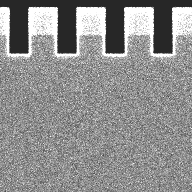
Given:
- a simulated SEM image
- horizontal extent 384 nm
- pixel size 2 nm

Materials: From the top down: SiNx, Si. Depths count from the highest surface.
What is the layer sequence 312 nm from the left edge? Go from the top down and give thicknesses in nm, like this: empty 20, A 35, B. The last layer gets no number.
empty 92, Si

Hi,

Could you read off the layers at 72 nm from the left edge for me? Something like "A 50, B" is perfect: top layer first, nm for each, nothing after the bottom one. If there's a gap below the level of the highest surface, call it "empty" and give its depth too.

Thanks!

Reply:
SiNx 54, Si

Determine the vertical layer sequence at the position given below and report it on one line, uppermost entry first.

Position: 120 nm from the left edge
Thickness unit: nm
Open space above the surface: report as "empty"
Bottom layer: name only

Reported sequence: empty 92, Si